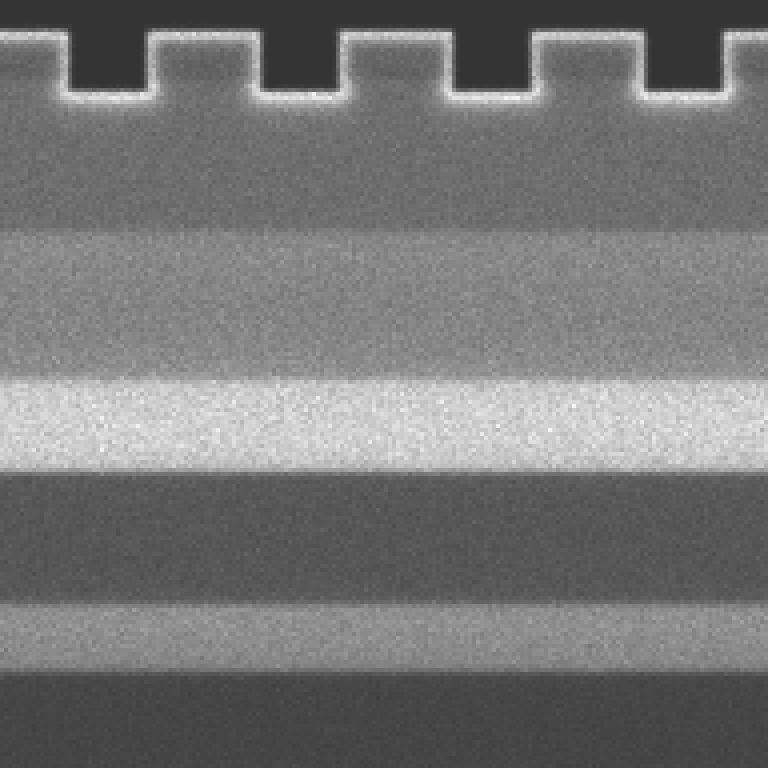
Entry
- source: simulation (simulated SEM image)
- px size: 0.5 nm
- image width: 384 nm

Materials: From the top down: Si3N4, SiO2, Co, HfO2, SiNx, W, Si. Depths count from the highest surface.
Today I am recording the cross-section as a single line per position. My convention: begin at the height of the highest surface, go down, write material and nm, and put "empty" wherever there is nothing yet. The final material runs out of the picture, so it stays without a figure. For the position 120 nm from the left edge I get Si3N4 24, SiO2 76, Co 74, HfO2 46, SiNx 66, W 34, Si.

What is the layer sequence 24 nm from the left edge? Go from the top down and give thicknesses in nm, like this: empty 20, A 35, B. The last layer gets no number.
Si3N4 24, SiO2 76, Co 74, HfO2 46, SiNx 66, W 34, Si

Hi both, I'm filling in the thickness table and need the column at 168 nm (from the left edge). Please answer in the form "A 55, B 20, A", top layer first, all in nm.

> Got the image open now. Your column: empty 30, SiO2 70, Co 74, HfO2 46, SiNx 66, W 34, Si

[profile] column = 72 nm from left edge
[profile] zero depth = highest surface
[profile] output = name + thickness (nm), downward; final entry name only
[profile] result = empty 30, SiO2 70, Co 74, HfO2 46, SiNx 66, W 34, Si